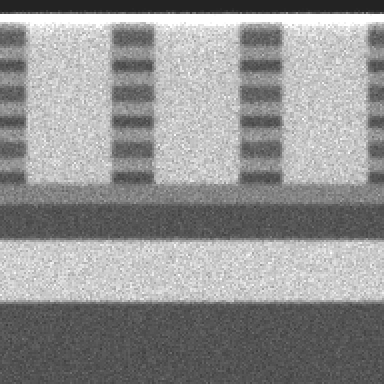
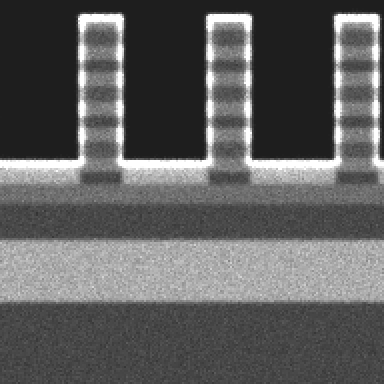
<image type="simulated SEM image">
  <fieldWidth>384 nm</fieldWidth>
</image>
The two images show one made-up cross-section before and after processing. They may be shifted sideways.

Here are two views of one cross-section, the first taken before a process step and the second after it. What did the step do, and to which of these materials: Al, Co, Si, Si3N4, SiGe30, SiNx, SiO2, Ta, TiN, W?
It removed Co.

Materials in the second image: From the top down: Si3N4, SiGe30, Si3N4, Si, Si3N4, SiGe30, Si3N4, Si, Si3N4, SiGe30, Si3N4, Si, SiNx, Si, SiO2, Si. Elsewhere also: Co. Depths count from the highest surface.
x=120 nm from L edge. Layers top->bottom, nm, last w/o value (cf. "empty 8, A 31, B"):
Si3N4 14, SiGe30 16, Si3N4 14, Si 12, Si3N4 14, SiGe30 16, Si3N4 14, Si 12, Si3N4 14, SiGe30 16, Si3N4 14, Si 12, SiNx 20, Si 36, SiO2 62, Si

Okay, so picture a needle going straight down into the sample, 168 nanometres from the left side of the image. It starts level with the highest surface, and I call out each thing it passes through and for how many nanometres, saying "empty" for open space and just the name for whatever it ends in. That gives empty 146, Co 22, SiNx 20, Si 36, SiO2 62, Si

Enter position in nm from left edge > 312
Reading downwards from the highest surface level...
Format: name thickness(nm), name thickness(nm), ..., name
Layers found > empty 146, Co 22, SiNx 20, Si 36, SiO2 62, Si